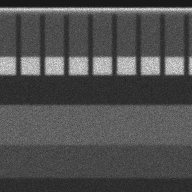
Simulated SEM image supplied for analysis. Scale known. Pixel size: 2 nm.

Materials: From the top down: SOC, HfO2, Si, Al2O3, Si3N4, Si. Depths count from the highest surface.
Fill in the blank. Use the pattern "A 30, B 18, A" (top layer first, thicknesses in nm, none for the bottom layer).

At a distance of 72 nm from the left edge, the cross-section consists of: SOC 98, HfO2 36, Si 60, Al2O3 80, Si3N4 66, Si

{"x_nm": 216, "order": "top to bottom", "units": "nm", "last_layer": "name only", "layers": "SOC 98, HfO2 36, Si 60, Al2O3 80, Si3N4 66, Si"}